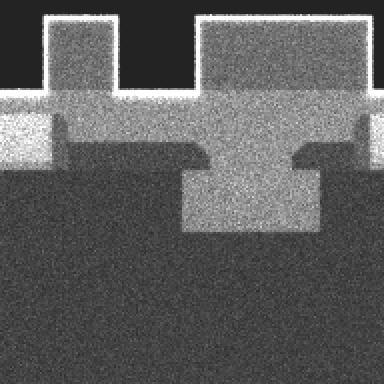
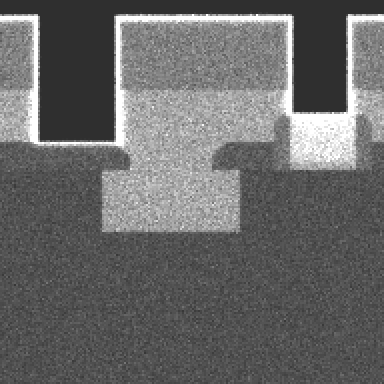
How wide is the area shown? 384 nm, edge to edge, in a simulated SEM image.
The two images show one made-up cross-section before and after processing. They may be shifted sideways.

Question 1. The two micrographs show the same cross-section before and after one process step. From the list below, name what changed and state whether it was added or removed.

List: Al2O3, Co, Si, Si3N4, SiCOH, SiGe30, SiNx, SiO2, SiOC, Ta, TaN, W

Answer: SiO2, removed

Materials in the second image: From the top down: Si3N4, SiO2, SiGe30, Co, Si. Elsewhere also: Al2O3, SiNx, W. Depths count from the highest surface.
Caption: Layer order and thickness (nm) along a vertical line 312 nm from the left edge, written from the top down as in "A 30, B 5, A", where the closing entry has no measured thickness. empty 98, W 48, Al2O3 8, Si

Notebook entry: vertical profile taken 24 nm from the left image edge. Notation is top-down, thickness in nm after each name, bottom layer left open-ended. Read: Si3N4 74, SiO2 52, SiGe30 28, Si